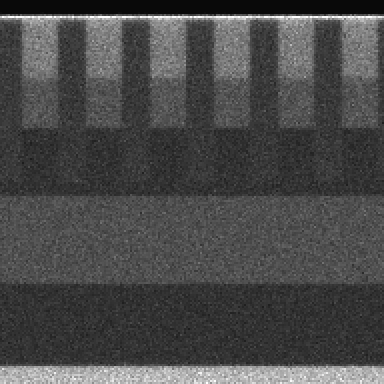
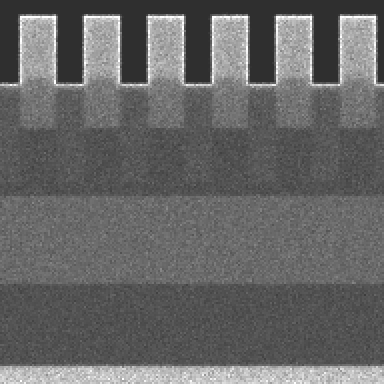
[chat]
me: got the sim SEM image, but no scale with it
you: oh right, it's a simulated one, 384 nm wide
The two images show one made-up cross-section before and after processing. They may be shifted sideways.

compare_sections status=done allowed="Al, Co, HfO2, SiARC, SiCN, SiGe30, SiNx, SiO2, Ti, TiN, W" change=removed material="TiN"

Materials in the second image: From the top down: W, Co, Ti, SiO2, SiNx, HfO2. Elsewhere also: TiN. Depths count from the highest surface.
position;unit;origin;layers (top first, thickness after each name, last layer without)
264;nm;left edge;empty 68, TiN 98, Ti 14, SiO2 88, SiNx 82, HfO2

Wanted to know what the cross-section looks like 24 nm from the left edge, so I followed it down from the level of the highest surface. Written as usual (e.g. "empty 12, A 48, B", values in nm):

W 62, Co 50, Ti 68, SiO2 88, SiNx 82, HfO2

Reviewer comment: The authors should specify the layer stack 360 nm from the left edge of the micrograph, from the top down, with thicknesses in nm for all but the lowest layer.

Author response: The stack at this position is W 62, Co 50, Ti 68, SiO2 88, SiNx 82, HfO2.